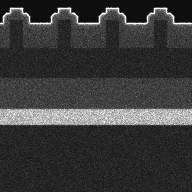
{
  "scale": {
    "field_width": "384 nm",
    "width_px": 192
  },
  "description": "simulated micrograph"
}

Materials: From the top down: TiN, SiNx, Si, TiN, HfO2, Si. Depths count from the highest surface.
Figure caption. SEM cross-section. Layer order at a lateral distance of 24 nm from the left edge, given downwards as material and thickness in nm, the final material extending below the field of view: TiN 24, Si 116, TiN 62, HfO2 32, Si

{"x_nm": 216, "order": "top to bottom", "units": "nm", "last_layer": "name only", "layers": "TiN 24, Si 116, TiN 62, HfO2 32, Si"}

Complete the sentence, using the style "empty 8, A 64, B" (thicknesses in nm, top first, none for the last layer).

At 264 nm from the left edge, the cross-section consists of empty 30, TiN 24, SiNx 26, Si 60, TiN 62, HfO2 32, Si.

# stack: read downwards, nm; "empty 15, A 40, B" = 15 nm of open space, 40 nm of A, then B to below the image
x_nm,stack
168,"empty 30, TiN 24, SiNx 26, Si 60, TiN 62, HfO2 32, Si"